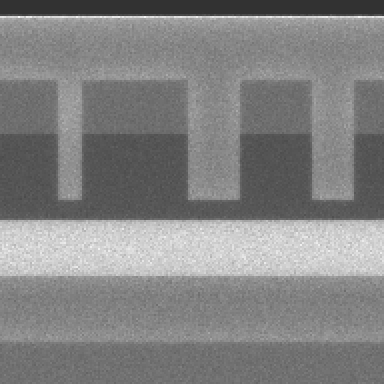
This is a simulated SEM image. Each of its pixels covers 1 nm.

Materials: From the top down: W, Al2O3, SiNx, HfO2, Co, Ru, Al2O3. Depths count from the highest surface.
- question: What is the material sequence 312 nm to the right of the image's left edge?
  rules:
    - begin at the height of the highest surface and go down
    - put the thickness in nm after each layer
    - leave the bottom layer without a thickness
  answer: W 184, SiNx 20, HfO2 56, Co 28, Ru 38, Al2O3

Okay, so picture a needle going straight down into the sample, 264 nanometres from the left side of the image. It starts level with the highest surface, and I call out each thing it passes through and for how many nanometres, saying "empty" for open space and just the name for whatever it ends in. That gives W 64, Al2O3 54, SiNx 86, HfO2 56, Co 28, Ru 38, Al2O3